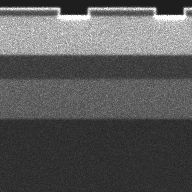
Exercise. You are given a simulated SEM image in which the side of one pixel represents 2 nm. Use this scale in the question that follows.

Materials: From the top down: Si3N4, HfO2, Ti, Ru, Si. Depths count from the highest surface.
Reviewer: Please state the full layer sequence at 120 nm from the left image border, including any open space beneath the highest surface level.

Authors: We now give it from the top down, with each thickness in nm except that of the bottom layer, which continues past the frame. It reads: empty 16, HfO2 78, Ti 48, Ru 80, Si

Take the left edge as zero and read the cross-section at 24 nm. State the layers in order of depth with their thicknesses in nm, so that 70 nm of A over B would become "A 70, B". Si3N4 16, HfO2 78, Ti 48, Ru 80, Si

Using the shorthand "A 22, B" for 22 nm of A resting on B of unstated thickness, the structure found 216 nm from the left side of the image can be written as Si3N4 16, HfO2 78, Ti 48, Ru 80, Si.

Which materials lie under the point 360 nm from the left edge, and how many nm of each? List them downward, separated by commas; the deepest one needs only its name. empty 16, HfO2 78, Ti 48, Ru 80, Si